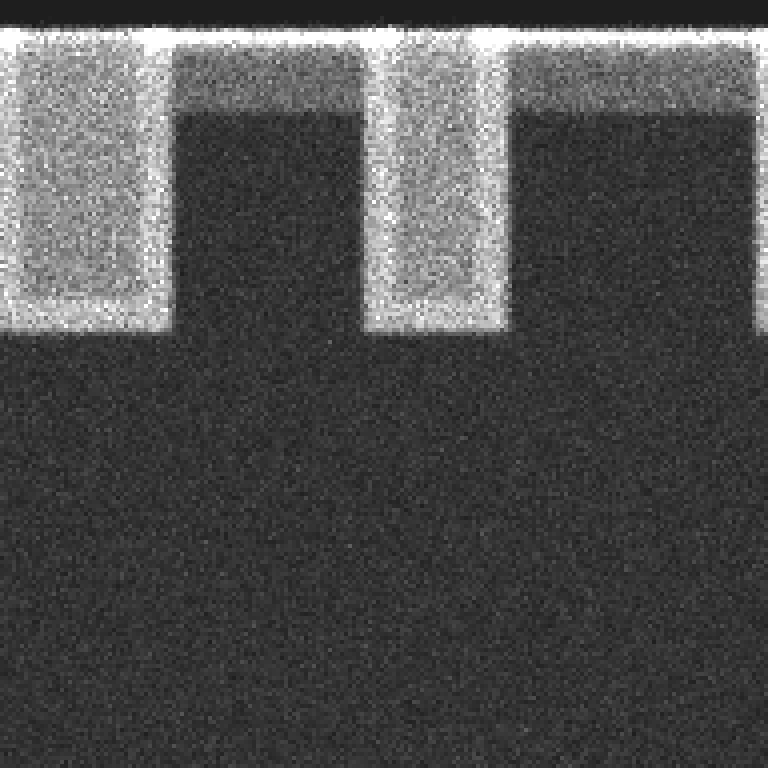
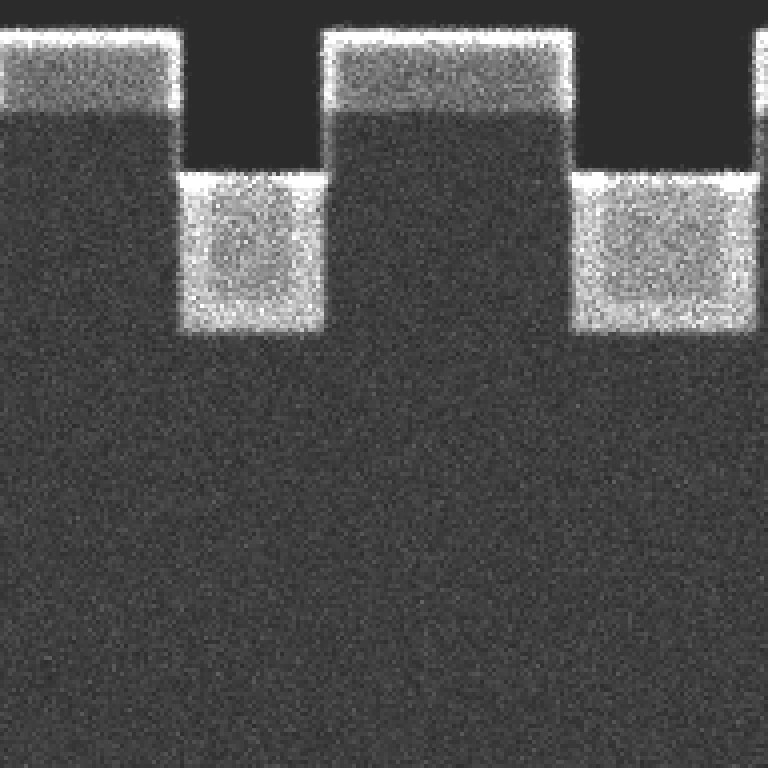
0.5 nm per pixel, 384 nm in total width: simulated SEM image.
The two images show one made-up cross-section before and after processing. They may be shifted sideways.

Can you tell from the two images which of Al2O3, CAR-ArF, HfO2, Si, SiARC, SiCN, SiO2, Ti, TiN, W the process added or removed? Yes, it removed HfO2 and W.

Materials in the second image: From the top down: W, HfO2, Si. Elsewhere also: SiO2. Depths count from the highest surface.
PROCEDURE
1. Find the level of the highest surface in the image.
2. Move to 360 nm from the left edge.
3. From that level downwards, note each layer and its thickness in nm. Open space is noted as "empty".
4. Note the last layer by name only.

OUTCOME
empty 72, W 62, HfO2 16, Si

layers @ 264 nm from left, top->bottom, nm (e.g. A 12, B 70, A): SiO2 40, Si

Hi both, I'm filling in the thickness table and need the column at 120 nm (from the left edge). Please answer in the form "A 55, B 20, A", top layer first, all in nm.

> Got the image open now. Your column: empty 72, W 62, HfO2 16, Si